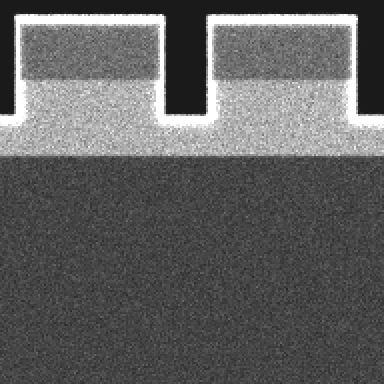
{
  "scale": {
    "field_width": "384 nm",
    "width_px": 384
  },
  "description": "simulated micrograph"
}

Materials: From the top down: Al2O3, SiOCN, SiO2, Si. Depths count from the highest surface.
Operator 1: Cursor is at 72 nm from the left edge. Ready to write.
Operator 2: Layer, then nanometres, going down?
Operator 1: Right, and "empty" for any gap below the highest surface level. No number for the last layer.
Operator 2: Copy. Al2O3 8, SiOCN 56, SiO2 76, Si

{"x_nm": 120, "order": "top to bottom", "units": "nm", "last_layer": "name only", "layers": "Al2O3 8, SiOCN 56, SiO2 76, Si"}